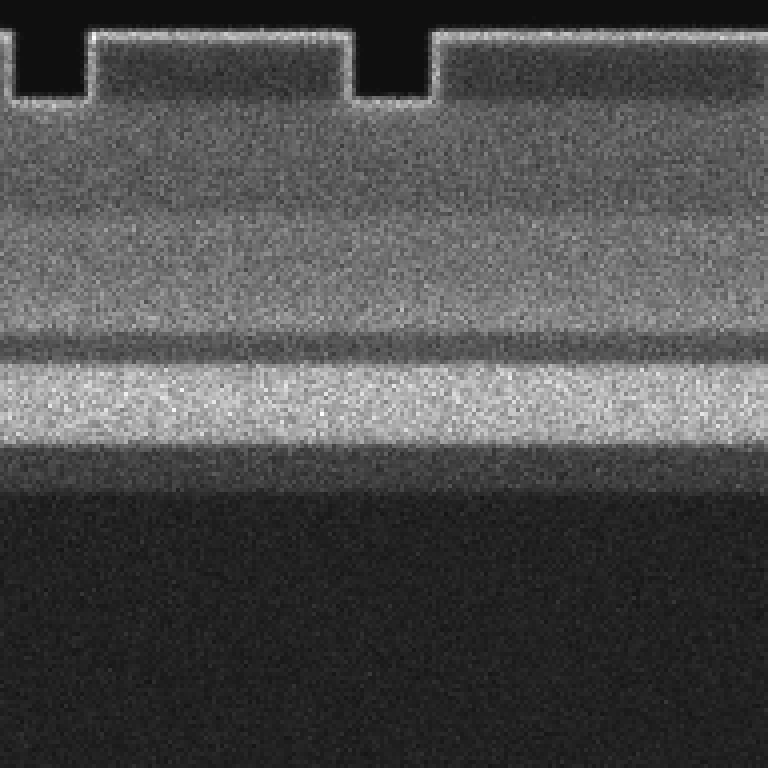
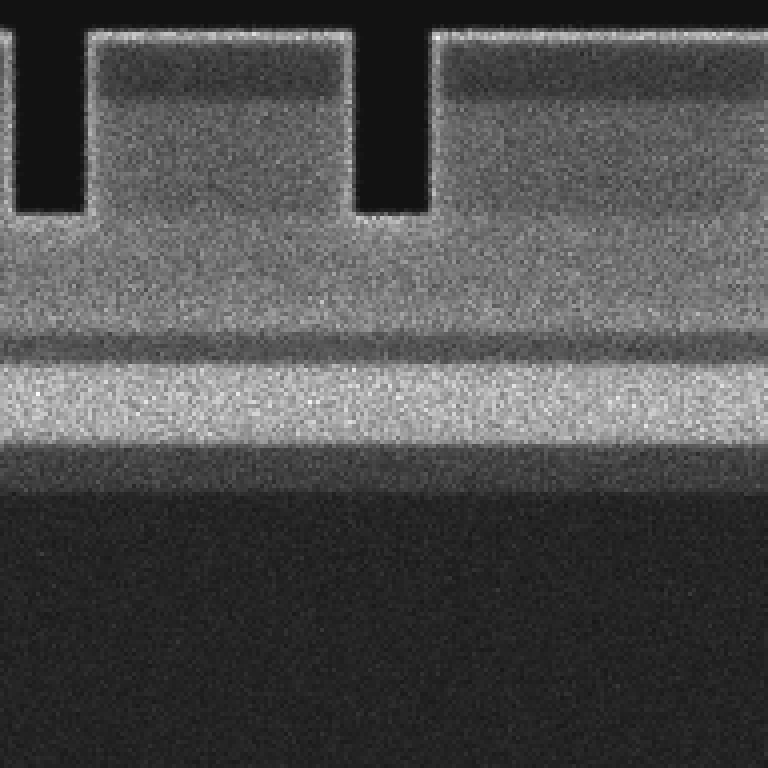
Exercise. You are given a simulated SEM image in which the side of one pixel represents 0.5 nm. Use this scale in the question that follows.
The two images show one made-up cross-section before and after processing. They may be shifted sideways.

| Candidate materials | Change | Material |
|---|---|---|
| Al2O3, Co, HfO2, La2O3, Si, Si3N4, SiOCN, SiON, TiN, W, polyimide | removed | Co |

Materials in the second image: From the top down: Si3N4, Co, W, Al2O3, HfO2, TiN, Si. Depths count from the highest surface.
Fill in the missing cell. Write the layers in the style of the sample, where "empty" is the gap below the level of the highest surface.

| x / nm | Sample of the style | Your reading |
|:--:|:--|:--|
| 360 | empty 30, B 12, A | Si3N4 34, Co 58, W 58, Al2O3 16, HfO2 40, TiN 24, Si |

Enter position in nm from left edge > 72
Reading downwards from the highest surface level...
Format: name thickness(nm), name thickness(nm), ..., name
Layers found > Si3N4 34, Co 58, W 58, Al2O3 16, HfO2 40, TiN 24, Si